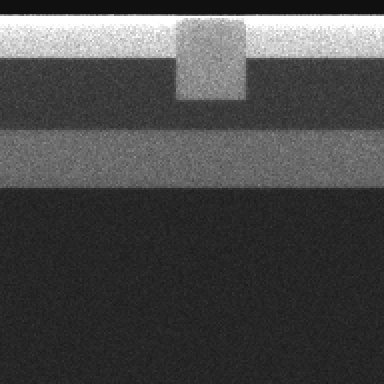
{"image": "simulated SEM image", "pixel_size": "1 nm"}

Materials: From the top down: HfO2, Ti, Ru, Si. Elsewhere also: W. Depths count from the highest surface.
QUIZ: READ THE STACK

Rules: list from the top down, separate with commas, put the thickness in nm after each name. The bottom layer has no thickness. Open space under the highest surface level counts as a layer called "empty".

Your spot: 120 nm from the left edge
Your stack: HfO2 42, Ti 72, Ru 58, Si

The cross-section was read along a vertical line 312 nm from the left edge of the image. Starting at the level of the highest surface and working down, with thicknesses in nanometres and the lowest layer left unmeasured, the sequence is HfO2 42, Ti 72, Ru 58, Si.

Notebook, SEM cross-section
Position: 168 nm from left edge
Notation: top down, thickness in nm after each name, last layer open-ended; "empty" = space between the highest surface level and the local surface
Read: HfO2 42, Ti 72, Ru 58, Si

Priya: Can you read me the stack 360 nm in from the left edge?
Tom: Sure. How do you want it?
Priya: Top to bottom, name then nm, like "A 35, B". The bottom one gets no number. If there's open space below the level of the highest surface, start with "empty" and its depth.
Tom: HfO2 42, Ti 72, Ru 58, Si